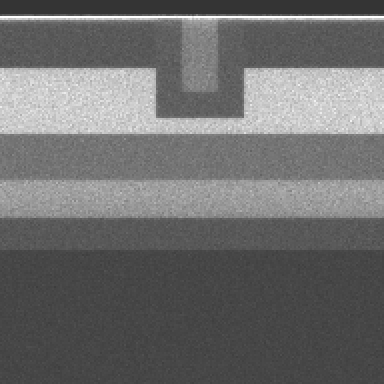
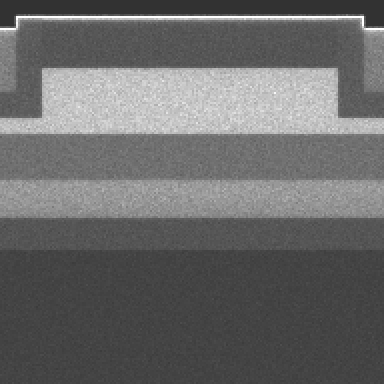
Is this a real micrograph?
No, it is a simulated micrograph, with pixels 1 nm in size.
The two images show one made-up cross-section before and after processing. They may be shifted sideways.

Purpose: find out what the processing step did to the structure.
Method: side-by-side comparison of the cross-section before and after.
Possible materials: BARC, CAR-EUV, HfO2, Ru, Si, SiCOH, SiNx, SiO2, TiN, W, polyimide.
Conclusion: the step removed Ru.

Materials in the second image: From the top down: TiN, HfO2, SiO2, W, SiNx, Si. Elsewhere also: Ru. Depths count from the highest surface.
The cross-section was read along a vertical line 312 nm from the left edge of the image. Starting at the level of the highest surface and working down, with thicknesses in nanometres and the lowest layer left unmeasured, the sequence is SiNx 52, HfO2 66, SiO2 46, W 38, SiNx 32, Si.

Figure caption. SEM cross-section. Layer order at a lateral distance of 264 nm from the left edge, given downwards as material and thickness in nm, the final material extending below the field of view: SiNx 52, HfO2 66, SiO2 46, W 38, SiNx 32, Si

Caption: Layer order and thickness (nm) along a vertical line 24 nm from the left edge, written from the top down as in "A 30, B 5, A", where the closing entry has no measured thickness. TiN 102, HfO2 16, SiO2 46, W 38, SiNx 32, Si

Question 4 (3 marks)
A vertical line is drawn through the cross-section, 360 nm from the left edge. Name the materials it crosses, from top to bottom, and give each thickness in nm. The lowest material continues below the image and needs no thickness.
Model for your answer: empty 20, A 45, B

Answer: TiN 102, HfO2 16, SiO2 46, W 38, SiNx 32, Si